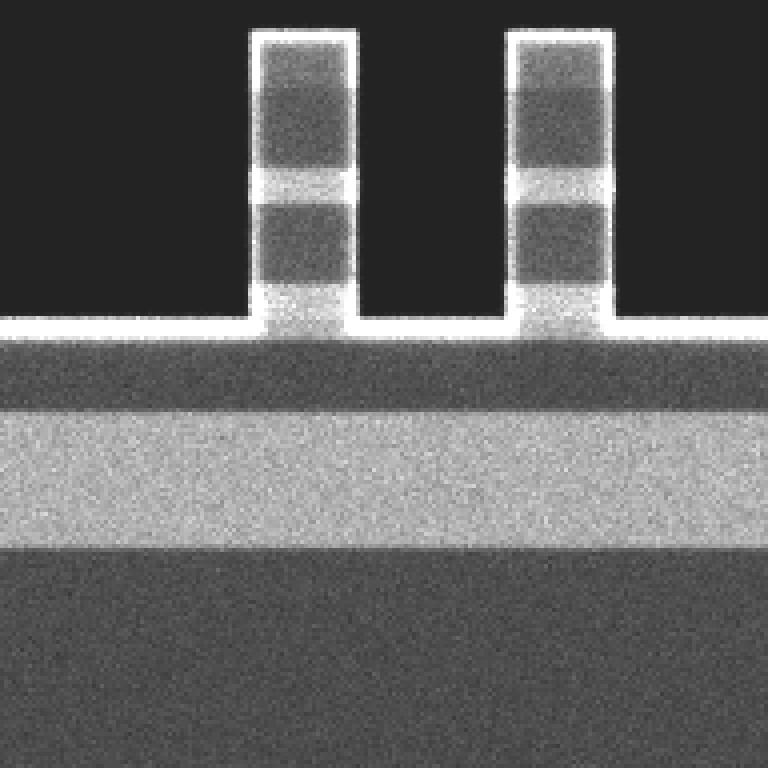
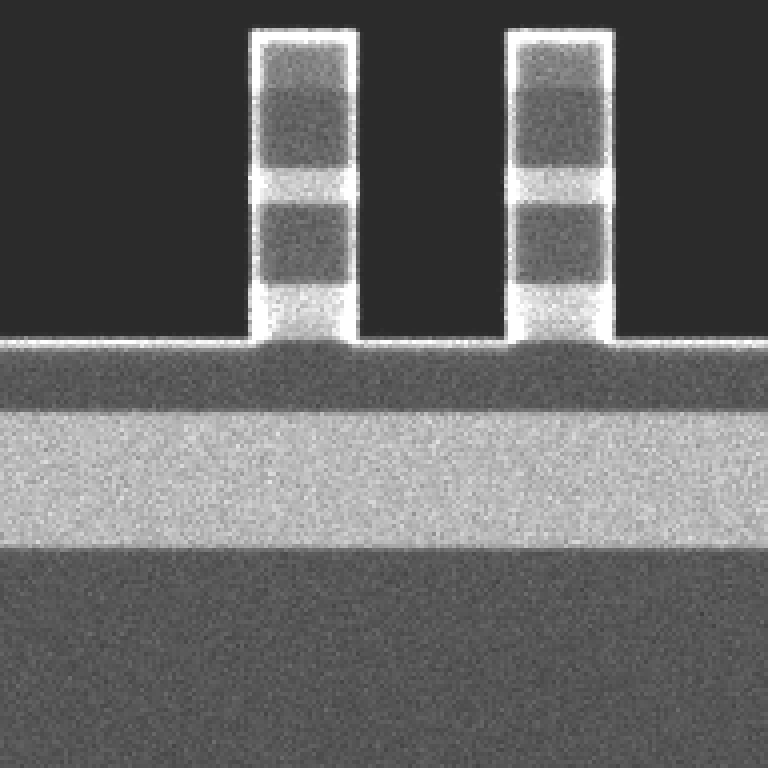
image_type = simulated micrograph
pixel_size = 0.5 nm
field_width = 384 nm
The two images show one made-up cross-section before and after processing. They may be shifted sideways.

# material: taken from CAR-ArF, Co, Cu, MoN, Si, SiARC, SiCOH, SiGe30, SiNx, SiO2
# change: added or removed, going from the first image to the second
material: SiO2
change: removed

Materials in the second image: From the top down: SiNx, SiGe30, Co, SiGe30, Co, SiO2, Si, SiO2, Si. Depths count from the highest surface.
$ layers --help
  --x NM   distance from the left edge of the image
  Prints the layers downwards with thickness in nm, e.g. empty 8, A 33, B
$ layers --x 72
empty 154, Si 36, SiO2 68, Si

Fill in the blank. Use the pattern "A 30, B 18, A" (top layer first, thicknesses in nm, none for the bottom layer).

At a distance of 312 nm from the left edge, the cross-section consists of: empty 154, Si 36, SiO2 68, Si